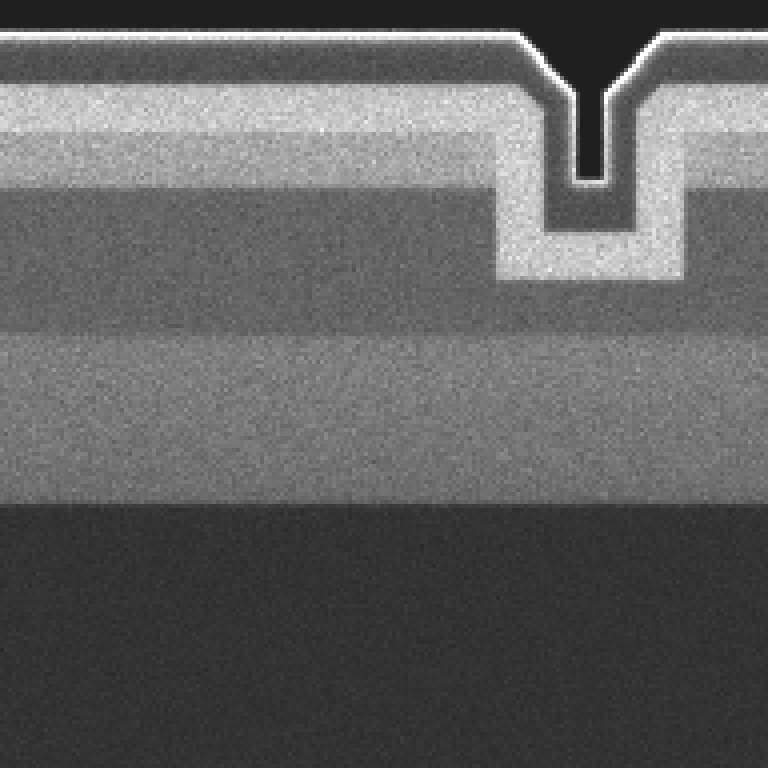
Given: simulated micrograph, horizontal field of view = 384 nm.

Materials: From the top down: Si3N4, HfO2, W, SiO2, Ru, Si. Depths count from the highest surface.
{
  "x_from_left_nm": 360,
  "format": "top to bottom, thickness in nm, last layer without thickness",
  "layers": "Si3N4 26, HfO2 24, W 28, SiO2 74, Ru 84, Si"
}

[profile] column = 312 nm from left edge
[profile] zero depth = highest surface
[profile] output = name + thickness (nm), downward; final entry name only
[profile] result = empty 20, Si3N4 80, HfO2 24, SiO2 28, Ru 84, Si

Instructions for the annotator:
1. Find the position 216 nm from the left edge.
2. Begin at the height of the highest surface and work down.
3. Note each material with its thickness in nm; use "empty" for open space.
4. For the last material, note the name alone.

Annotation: Si3N4 26, HfO2 24, W 28, SiO2 74, Ru 84, Si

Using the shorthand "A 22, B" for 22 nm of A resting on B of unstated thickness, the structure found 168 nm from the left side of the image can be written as Si3N4 26, HfO2 24, W 28, SiO2 74, Ru 84, Si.